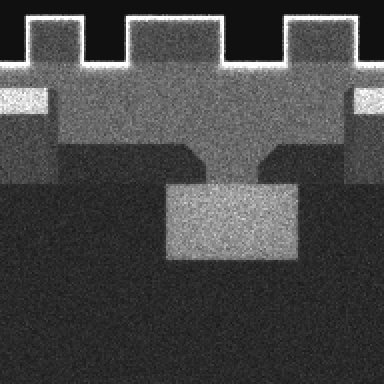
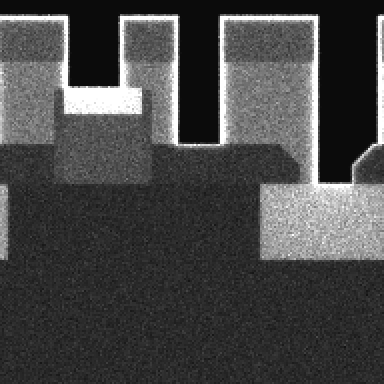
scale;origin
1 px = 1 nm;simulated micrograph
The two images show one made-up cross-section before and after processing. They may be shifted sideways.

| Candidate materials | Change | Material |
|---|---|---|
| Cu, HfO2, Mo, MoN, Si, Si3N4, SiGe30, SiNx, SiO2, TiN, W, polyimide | removed | SiO2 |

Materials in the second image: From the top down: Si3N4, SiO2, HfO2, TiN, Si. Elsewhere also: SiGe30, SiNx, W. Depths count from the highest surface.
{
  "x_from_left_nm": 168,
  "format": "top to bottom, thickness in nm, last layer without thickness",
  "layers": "Si3N4 46, SiO2 82, SiGe30 40, Si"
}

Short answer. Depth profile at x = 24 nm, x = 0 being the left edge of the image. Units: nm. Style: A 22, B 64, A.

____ Si3N4 46, SiO2 82, SiGe30 40, Si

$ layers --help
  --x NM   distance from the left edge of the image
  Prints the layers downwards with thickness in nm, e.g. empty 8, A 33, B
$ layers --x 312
Si3N4 46, SiO2 122, W 76, Si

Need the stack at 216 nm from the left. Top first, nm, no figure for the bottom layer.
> empty 128, SiGe30 40, Si